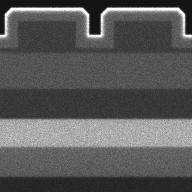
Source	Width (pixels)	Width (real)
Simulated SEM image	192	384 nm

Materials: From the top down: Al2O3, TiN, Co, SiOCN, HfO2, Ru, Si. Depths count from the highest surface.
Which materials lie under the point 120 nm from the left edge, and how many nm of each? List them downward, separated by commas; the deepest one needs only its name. Al2O3 26, TiN 64, Co 72, SiOCN 60, HfO2 56, Ru 60, Si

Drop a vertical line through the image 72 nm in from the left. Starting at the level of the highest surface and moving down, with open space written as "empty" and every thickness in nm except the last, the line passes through Al2O3 26, TiN 64, Co 72, SiOCN 60, HfO2 56, Ru 60, Si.